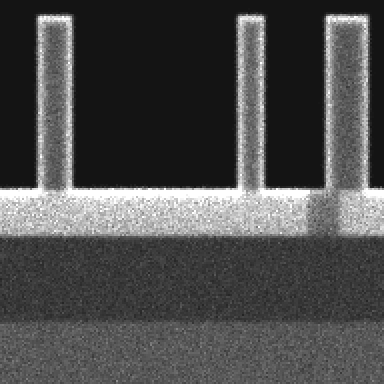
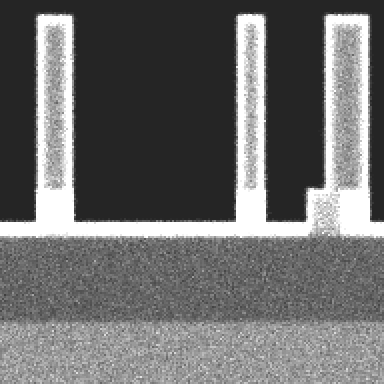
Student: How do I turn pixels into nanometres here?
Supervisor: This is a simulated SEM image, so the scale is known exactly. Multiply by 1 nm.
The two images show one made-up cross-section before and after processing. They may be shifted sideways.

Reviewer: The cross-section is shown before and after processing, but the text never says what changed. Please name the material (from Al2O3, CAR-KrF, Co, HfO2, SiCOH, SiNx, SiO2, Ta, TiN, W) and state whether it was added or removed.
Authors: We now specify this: HfO2, removed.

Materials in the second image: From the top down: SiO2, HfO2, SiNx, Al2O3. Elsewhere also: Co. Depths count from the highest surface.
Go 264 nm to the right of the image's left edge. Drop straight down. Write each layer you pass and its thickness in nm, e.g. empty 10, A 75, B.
empty 208, HfO2 12, SiNx 86, Al2O3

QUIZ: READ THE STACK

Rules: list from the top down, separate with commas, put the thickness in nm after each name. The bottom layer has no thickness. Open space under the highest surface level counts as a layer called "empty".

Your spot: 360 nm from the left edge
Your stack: SiO2 174, HfO2 46, SiNx 86, Al2O3